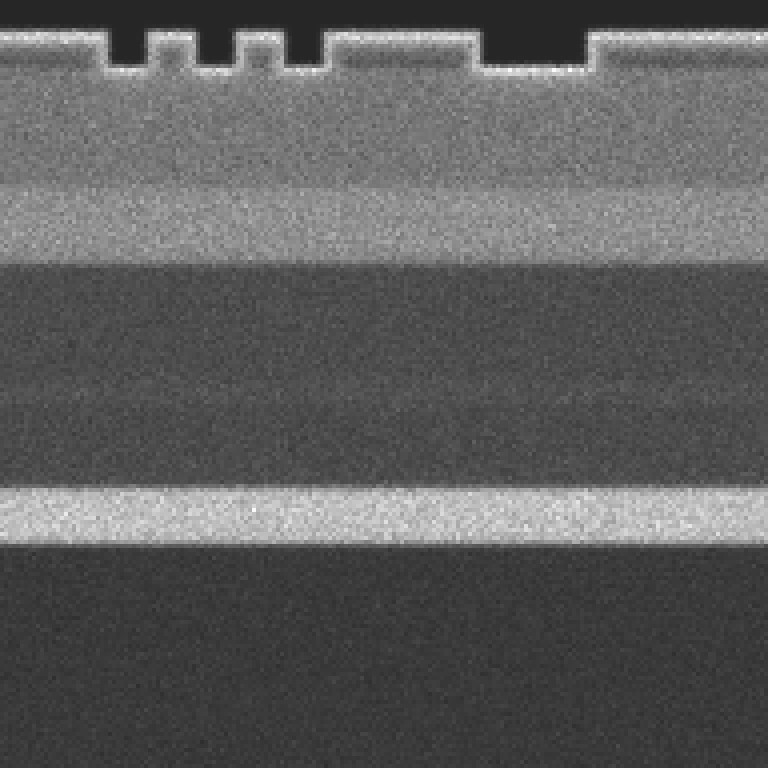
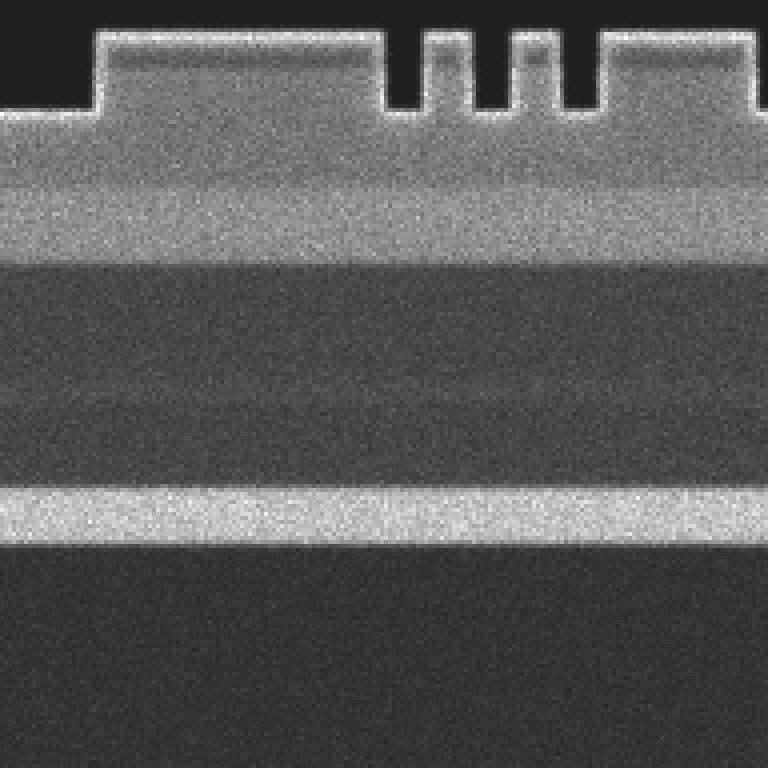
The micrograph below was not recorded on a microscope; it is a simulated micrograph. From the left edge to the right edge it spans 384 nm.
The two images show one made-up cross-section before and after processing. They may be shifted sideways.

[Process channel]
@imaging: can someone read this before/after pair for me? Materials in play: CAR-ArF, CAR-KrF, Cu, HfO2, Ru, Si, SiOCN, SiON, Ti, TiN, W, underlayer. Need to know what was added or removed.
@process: Ru removed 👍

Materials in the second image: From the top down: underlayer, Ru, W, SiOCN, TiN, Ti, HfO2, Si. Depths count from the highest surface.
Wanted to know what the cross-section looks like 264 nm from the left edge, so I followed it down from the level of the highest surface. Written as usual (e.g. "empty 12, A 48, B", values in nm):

underlayer 18, Ru 60, W 38, SiOCN 58, TiN 12, Ti 42, HfO2 28, Si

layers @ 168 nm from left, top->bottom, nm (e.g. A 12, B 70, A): underlayer 18, Ru 60, W 38, SiOCN 58, TiN 12, Ti 42, HfO2 28, Si